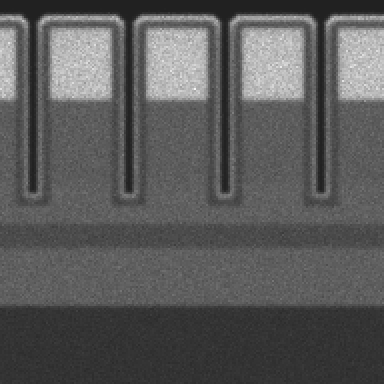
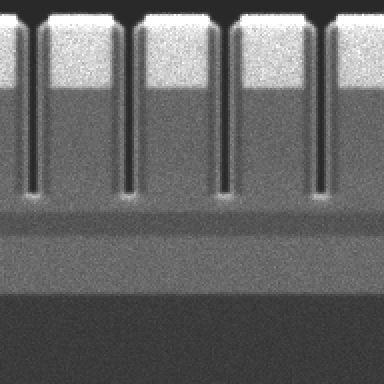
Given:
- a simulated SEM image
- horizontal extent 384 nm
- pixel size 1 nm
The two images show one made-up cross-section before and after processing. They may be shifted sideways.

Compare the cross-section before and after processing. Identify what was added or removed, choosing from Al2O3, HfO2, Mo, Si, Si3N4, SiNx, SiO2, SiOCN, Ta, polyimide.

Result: SiOCN removed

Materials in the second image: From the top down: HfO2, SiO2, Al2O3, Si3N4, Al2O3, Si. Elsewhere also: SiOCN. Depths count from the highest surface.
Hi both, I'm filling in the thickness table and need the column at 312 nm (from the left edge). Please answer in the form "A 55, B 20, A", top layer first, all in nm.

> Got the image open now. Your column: empty 10, SiOCN 168, Al2O3 18, Si3N4 24, Al2O3 58, Si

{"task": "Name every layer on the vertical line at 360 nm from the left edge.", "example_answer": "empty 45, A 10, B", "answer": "HfO2 72, SiO2 84, Al2O3 40, Si3N4 24, Al2O3 58, Si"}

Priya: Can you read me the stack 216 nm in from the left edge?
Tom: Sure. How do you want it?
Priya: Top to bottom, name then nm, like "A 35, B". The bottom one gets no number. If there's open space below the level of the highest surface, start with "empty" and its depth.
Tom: empty 10, SiOCN 168, Al2O3 18, Si3N4 24, Al2O3 58, Si